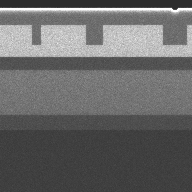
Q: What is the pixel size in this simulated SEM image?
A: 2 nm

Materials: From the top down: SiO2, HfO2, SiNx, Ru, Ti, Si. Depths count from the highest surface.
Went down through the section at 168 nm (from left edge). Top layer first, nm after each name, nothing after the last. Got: SiO2 34, HfO2 64, SiNx 26, Ru 90, Ti 30, Si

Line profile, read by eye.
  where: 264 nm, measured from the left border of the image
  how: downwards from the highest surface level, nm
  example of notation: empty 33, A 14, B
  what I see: SiO2 34, HfO2 64, SiNx 26, Ru 90, Ti 30, Si